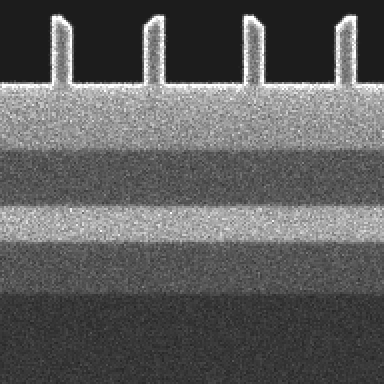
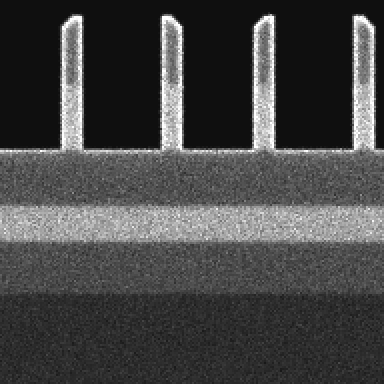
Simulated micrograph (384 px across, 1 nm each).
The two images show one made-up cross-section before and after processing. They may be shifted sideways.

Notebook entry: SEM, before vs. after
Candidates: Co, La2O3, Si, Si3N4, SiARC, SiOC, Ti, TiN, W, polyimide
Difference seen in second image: Co removed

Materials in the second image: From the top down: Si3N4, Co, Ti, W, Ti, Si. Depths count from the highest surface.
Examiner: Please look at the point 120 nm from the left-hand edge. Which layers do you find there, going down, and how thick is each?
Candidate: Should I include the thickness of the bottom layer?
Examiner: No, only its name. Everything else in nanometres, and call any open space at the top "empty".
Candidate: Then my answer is empty 134, Ti 56, W 36, Ti 52, Si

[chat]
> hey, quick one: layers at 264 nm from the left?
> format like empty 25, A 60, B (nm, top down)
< Si3N4 68, Co 66, Ti 56, W 36, Ti 52, Si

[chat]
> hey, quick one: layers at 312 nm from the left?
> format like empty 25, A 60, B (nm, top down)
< empty 134, Ti 56, W 36, Ti 52, Si